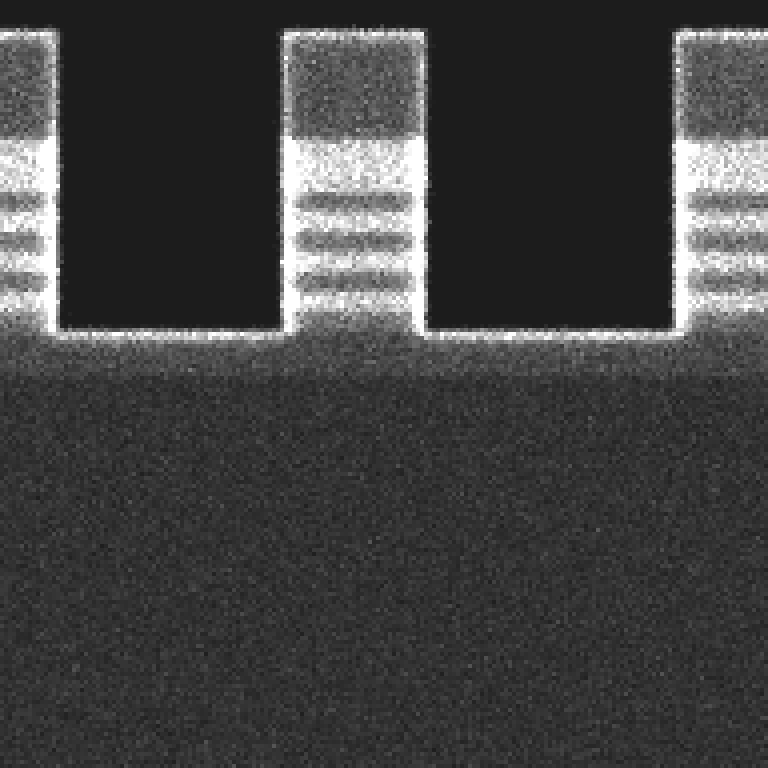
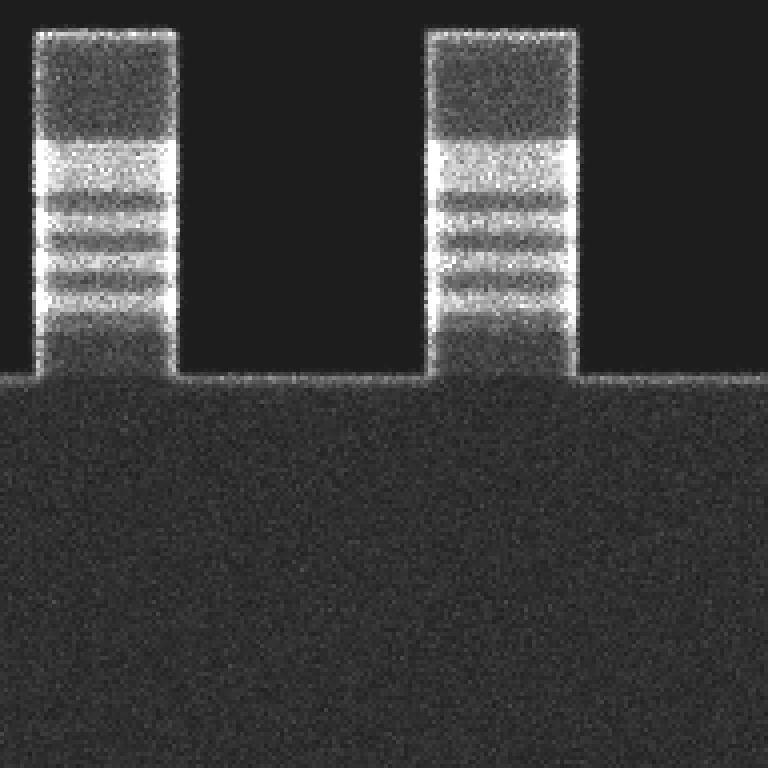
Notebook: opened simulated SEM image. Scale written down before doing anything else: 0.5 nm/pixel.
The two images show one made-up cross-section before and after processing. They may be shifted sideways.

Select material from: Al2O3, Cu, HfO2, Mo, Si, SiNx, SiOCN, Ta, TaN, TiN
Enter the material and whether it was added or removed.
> SiNx / removed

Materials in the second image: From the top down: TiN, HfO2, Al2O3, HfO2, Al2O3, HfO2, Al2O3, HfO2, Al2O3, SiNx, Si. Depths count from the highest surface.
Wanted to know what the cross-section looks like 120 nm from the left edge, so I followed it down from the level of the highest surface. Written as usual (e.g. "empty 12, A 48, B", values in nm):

empty 172, Si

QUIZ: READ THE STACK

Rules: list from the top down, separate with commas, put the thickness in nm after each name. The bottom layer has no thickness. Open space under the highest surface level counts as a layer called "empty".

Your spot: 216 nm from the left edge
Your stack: TiN 54, HfO2 26, Al2O3 10, HfO2 10, Al2O3 10, HfO2 10, Al2O3 10, HfO2 10, Al2O3 10, SiNx 22, Si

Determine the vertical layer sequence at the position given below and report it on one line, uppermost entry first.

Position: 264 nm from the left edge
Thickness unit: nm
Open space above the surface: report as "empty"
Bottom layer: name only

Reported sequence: TiN 54, HfO2 26, Al2O3 10, HfO2 10, Al2O3 10, HfO2 10, Al2O3 10, HfO2 10, Al2O3 10, SiNx 22, Si